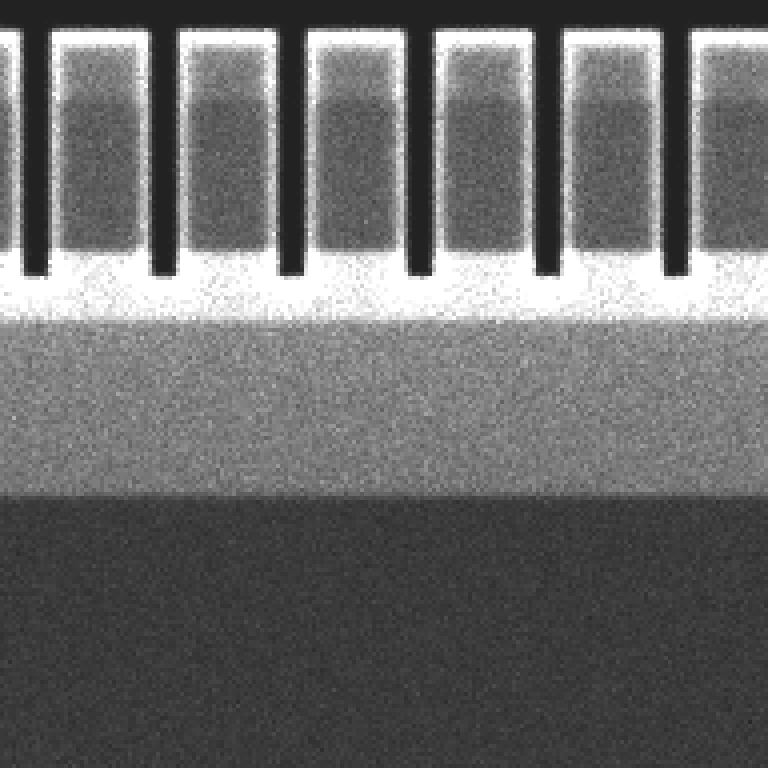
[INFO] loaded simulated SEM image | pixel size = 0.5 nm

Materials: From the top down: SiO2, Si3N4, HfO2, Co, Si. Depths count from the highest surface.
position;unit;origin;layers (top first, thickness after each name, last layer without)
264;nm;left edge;SiO2 34, Si3N4 76, HfO2 34, Co 88, Si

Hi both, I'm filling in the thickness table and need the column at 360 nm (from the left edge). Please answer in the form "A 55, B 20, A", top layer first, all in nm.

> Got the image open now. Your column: SiO2 34, Si3N4 76, HfO2 34, Co 88, Si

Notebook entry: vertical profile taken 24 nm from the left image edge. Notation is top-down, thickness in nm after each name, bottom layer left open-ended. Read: empty 124, HfO2 20, Co 88, Si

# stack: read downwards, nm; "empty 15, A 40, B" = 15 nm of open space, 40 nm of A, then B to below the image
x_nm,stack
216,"empty 124, HfO2 20, Co 88, Si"